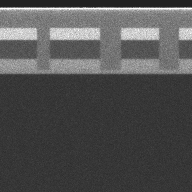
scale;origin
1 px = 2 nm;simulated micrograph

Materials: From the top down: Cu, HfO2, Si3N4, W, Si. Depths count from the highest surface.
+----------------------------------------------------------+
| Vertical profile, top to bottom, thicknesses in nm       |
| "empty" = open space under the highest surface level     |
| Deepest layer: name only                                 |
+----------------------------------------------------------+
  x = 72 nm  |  Cu 40, HfO2 24, Si3N4 38, W 30, Si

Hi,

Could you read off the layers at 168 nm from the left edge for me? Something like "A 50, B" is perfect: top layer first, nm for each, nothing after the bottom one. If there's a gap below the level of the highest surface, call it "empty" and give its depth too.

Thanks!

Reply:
Cu 40, HfO2 24, Si3N4 38, W 30, Si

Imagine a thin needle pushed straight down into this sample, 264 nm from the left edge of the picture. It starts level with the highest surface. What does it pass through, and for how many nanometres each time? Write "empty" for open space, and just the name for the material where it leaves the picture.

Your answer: Cu 40, HfO2 24, Si3N4 38, W 30, Si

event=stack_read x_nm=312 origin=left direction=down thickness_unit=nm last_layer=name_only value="Cu 40, HfO2 24, Si3N4 38, W 30, Si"